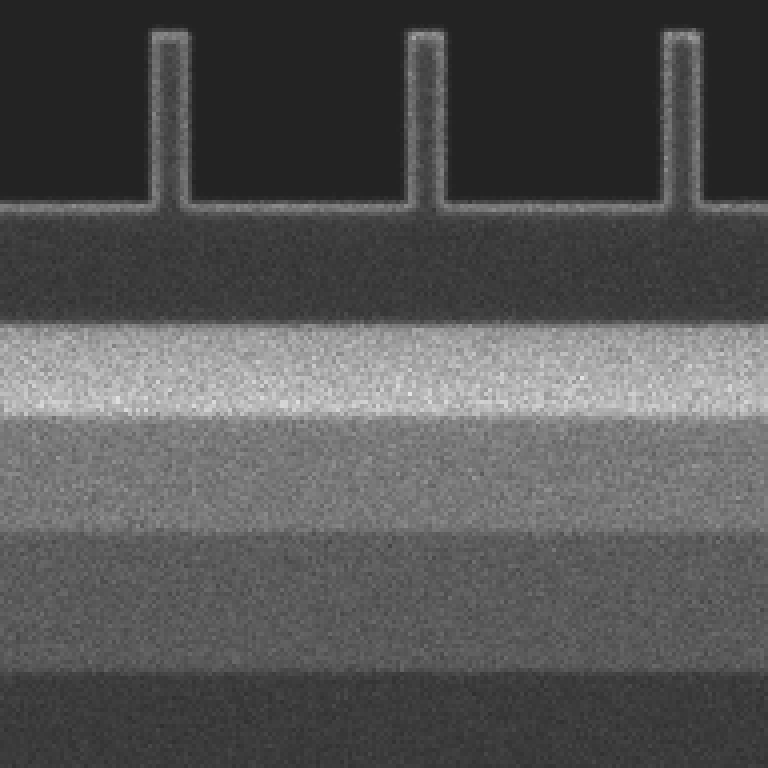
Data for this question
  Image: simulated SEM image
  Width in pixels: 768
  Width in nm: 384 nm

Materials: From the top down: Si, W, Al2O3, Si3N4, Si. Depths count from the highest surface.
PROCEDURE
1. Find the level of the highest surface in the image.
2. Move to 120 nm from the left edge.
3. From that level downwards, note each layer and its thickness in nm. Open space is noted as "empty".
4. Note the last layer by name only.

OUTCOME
empty 86, Si 60, W 46, Al2O3 58, Si3N4 70, Si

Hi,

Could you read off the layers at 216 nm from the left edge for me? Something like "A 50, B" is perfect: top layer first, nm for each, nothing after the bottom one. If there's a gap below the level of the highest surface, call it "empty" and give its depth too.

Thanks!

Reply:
Si 146, W 46, Al2O3 58, Si3N4 70, Si